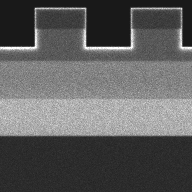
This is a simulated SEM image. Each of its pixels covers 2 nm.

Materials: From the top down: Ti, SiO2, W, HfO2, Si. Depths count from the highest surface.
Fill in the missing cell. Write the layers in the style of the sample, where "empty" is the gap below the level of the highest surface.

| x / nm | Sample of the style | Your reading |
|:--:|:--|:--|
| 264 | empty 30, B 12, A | Ti 42, SiO2 64, W 76, HfO2 74, Si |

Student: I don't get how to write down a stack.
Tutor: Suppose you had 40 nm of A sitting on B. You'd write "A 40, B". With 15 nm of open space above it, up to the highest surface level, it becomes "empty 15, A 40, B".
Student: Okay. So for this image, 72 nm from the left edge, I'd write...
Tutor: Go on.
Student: Ti 42, SiO2 64, W 76, HfO2 74, Si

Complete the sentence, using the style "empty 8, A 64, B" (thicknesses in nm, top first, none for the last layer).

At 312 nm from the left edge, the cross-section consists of Ti 42, SiO2 64, W 76, HfO2 74, Si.